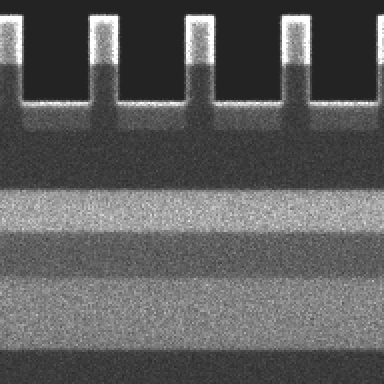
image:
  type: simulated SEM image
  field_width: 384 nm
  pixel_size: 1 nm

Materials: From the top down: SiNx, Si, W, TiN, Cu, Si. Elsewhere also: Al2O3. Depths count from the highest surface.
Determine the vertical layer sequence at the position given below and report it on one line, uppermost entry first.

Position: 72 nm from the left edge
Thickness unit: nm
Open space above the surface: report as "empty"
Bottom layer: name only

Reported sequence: empty 86, SiNx 28, Si 60, W 42, TiN 46, Cu 72, Si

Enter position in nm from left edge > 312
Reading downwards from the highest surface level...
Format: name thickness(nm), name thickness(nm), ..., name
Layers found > empty 86, SiNx 28, Si 60, W 42, TiN 46, Cu 72, Si